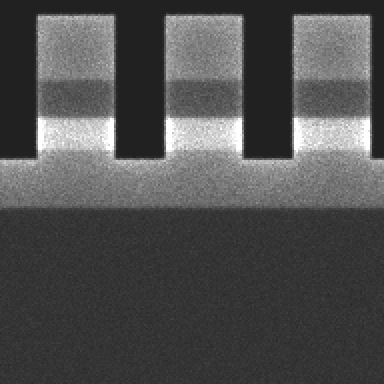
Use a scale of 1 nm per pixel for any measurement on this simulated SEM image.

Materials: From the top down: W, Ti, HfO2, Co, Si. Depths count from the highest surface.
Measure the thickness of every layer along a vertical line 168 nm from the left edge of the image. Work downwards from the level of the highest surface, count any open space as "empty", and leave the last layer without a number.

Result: W 64, Ti 38, HfO2 32, Co 58, Si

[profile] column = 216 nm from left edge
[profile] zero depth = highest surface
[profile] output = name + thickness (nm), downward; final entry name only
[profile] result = W 64, Ti 38, HfO2 32, Co 58, Si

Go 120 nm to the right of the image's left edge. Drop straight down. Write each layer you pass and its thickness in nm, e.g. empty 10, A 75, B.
empty 144, Co 48, Si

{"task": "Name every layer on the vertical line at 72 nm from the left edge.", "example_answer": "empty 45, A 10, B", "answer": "W 64, Ti 38, HfO2 32, Co 58, Si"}